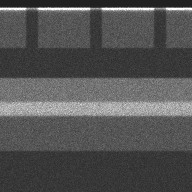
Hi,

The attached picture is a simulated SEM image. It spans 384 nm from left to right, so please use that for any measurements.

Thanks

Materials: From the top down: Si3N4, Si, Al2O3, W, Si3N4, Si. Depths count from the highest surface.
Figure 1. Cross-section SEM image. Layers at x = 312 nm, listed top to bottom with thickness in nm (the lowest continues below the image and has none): Si 140, Al2O3 48, W 28, Si3N4 70, Si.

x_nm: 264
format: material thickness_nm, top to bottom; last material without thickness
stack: Si3N4 80, Si 60, Al2O3 48, W 28, Si3N4 70, Si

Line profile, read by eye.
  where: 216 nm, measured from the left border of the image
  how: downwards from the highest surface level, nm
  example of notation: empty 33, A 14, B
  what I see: Si3N4 80, Si 60, Al2O3 48, W 28, Si3N4 70, Si